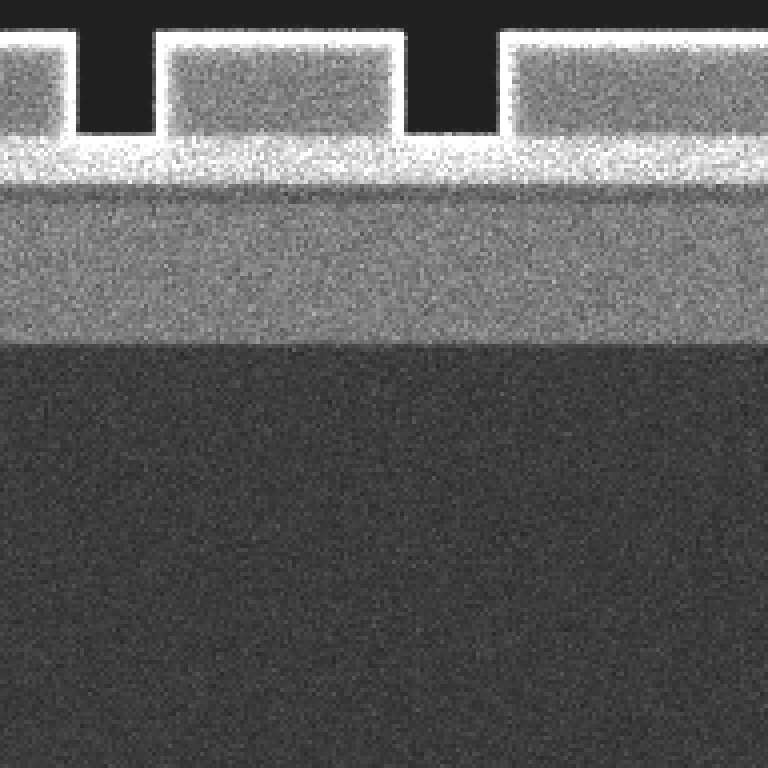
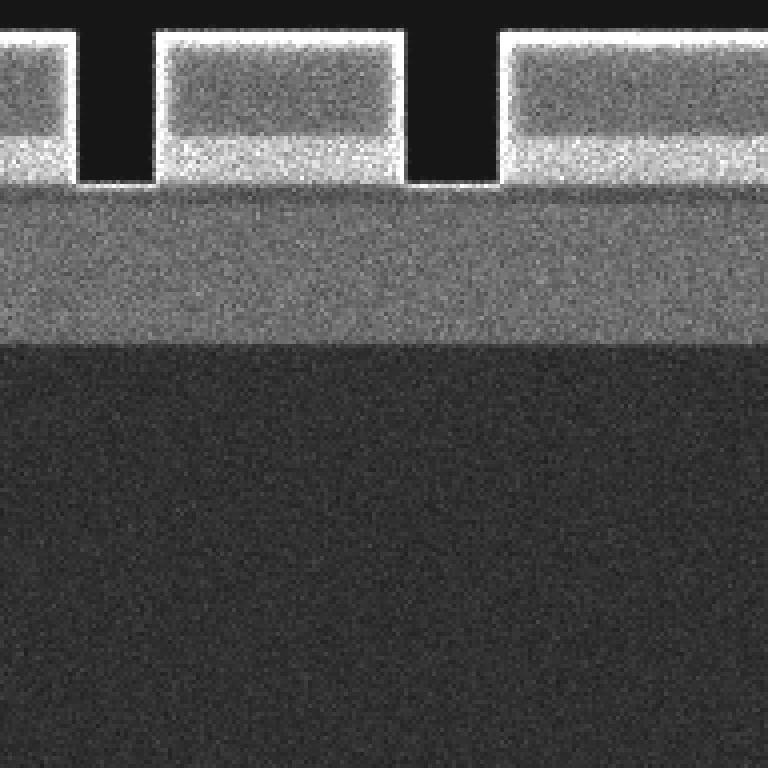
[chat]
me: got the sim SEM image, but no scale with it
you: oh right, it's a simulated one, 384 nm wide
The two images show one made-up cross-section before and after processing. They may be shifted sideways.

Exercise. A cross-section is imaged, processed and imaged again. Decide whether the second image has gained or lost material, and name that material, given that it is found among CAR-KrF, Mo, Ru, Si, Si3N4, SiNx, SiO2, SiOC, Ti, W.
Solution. removed: W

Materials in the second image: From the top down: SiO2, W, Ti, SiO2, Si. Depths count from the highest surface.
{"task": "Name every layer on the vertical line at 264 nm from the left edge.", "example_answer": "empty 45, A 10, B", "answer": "SiO2 52, W 24, Ti 10, SiO2 70, Si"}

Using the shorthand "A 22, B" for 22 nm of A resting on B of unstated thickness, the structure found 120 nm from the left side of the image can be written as SiO2 52, W 24, Ti 10, SiO2 70, Si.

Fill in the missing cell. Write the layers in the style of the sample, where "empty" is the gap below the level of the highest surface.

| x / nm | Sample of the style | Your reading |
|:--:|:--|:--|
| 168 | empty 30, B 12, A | SiO2 52, W 24, Ti 10, SiO2 70, Si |